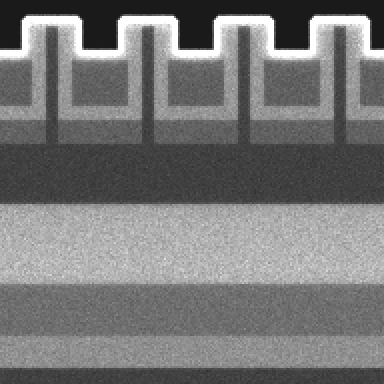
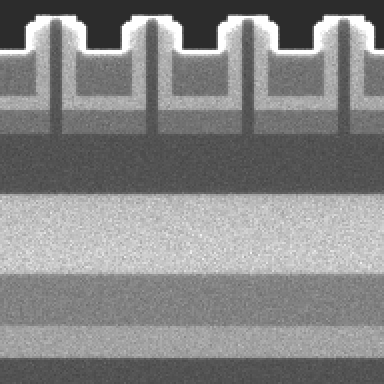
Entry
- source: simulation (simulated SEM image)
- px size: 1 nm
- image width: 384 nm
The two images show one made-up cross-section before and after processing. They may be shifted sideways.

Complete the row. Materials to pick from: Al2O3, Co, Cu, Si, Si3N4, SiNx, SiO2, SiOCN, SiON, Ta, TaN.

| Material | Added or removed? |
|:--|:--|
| SiO2 | removed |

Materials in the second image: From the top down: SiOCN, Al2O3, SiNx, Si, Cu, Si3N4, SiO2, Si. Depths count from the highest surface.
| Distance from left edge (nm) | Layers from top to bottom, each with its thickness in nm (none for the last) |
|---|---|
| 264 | Al2O3 94, SiNx 24, Si 60, Cu 80, Si3N4 52, SiO2 32, Si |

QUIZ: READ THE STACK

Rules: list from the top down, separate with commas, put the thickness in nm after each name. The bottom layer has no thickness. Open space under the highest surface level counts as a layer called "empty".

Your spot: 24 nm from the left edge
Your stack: empty 34, SiOCN 46, Al2O3 14, SiNx 24, Si 60, Cu 80, Si3N4 52, SiO2 32, Si